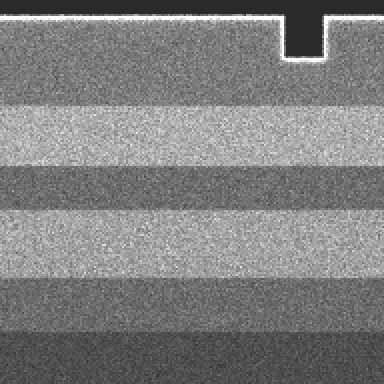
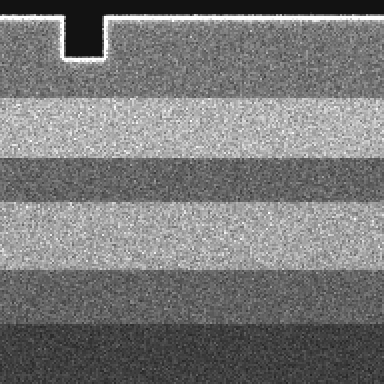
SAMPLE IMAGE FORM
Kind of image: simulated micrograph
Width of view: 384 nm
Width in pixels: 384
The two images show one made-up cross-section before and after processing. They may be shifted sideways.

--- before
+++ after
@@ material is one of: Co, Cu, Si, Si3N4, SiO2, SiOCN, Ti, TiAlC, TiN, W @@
TiN removed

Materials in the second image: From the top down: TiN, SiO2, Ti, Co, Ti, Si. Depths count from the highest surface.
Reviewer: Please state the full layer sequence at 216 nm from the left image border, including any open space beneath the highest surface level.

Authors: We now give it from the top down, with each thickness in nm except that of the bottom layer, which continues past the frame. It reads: TiN 82, SiO2 60, Ti 44, Co 68, Ti 54, Si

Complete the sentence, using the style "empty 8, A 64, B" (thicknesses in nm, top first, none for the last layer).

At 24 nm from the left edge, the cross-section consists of TiN 82, SiO2 60, Ti 44, Co 68, Ti 54, Si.